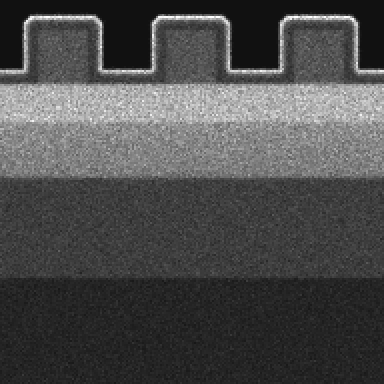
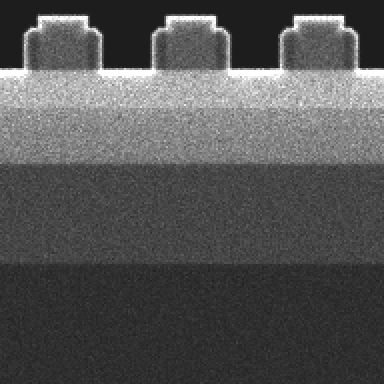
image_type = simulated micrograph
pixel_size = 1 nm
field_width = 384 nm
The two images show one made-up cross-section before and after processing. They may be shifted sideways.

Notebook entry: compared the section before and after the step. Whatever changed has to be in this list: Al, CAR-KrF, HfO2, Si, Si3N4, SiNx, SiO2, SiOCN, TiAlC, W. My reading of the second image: SiNx removed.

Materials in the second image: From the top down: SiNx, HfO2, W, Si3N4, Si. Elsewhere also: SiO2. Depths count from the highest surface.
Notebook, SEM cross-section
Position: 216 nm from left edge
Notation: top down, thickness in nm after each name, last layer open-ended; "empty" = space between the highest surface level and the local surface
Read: empty 12, SiNx 42, HfO2 38, W 56, Si3N4 100, Si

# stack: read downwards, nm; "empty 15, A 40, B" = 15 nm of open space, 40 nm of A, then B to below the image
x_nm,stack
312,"SiO2 54, HfO2 38, W 56, Si3N4 100, Si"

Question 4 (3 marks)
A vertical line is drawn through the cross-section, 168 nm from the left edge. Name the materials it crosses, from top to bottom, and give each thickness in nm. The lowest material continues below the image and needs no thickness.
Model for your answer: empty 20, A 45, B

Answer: SiO2 54, HfO2 38, W 56, Si3N4 100, Si